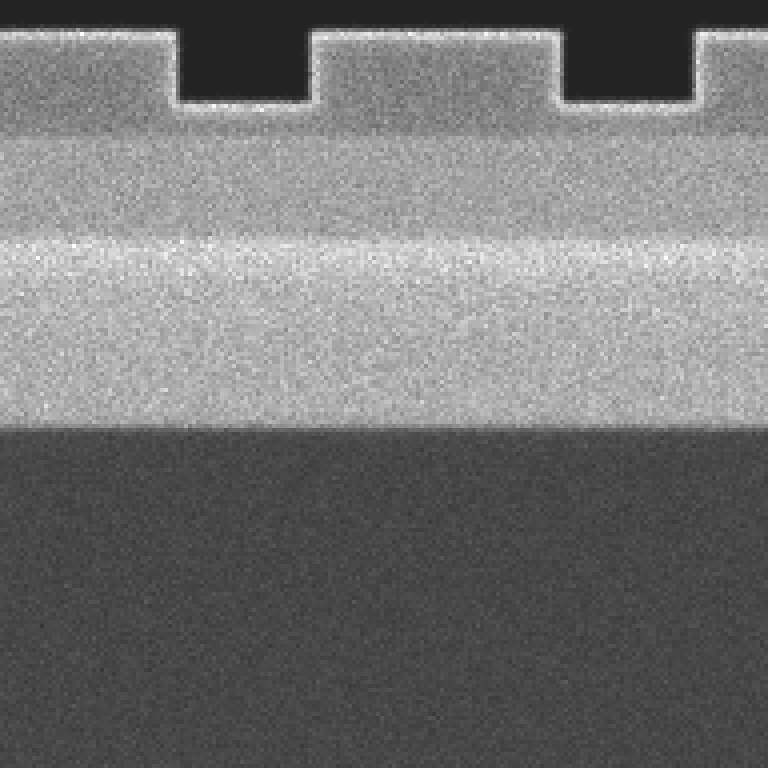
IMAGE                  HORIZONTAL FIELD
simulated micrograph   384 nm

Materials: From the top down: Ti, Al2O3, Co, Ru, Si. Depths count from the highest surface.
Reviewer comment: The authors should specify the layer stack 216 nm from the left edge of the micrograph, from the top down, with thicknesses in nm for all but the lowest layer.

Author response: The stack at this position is Ti 52, Al2O3 52, Co 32, Ru 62, Si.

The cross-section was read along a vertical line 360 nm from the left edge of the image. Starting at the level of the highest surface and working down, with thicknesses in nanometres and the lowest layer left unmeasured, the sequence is Ti 52, Al2O3 52, Co 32, Ru 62, Si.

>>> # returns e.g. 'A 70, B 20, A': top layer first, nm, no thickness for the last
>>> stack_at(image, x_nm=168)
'Ti 52, Al2O3 52, Co 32, Ru 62, Si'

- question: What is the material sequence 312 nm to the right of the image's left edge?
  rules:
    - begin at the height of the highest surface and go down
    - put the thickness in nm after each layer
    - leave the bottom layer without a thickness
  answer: empty 36, Ti 16, Al2O3 52, Co 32, Ru 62, Si